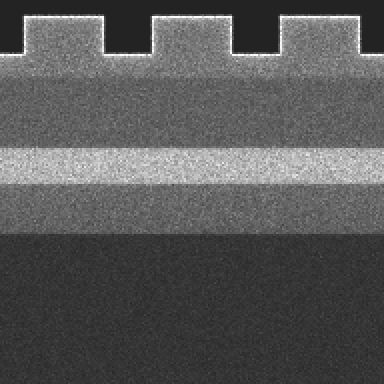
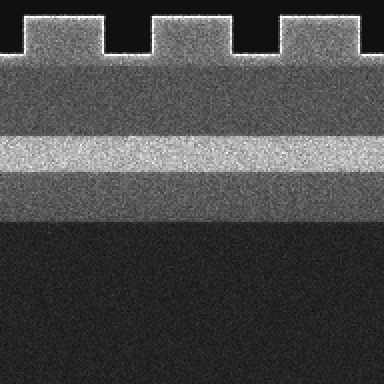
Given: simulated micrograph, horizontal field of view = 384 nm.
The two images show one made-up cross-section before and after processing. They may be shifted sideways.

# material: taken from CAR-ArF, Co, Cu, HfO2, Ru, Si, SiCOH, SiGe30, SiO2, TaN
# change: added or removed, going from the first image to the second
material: Ru
change: removed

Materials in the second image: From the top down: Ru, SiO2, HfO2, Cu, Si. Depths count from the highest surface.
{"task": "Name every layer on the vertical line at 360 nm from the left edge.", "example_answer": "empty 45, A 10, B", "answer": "empty 38, Ru 12, SiO2 70, HfO2 36, Cu 50, Si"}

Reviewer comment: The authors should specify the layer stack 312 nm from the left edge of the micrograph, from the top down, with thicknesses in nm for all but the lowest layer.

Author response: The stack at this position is Ru 50, SiO2 70, HfO2 36, Cu 50, Si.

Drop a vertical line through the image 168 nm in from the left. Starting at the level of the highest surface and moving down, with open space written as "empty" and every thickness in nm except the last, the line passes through Ru 50, SiO2 70, HfO2 36, Cu 50, Si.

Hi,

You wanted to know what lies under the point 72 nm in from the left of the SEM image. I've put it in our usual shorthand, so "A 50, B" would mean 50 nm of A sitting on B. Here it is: Ru 50, SiO2 70, HfO2 36, Cu 50, Si